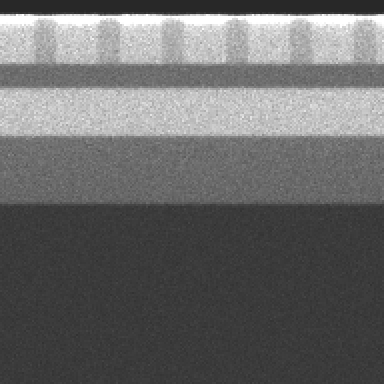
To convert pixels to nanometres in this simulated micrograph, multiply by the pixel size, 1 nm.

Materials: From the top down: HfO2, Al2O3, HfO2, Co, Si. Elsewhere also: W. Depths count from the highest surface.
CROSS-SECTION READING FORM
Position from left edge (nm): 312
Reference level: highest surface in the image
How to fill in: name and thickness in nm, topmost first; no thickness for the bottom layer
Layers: HfO2 48, Al2O3 24, HfO2 48, Co 68, Si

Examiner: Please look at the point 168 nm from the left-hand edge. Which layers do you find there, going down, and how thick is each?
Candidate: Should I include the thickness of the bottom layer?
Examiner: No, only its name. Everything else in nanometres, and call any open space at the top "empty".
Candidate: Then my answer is W 48, Al2O3 24, HfO2 48, Co 68, Si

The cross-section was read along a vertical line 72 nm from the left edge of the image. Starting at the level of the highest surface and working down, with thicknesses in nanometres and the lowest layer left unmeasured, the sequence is HfO2 48, Al2O3 24, HfO2 48, Co 68, Si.